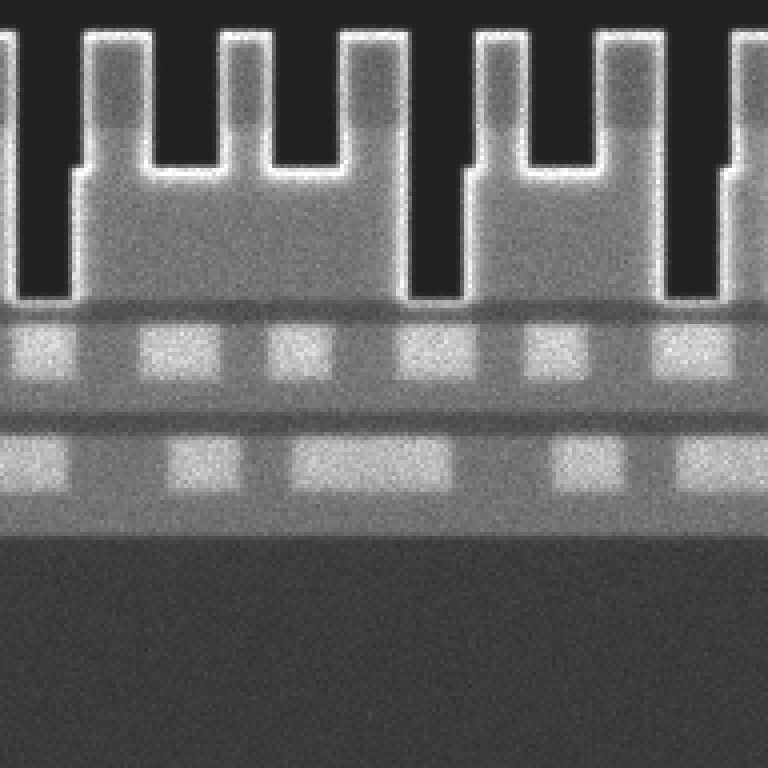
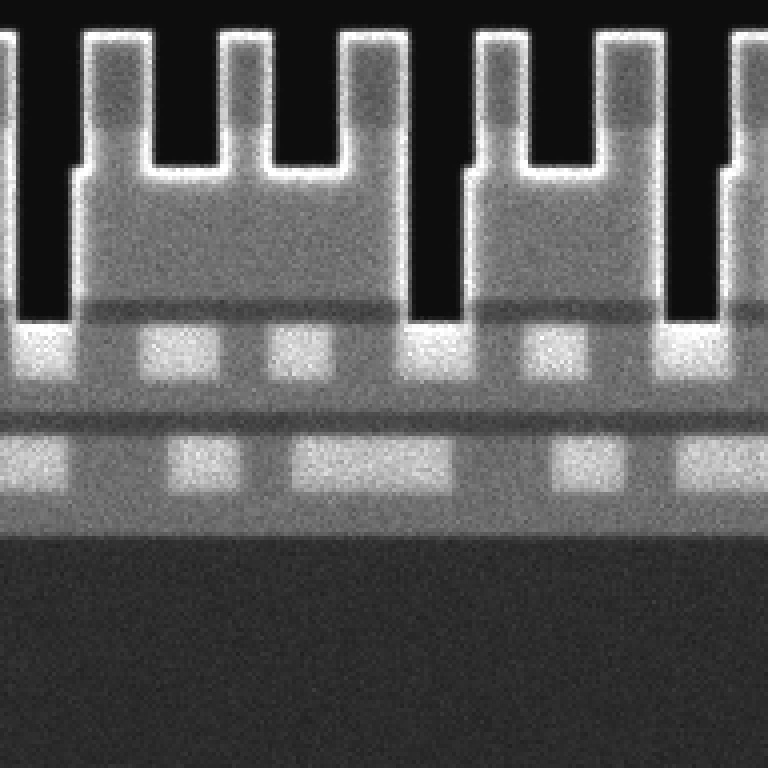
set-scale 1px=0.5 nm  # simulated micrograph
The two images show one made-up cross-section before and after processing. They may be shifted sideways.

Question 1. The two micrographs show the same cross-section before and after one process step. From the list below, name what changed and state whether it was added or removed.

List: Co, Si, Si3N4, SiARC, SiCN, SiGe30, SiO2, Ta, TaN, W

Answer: SiCN, removed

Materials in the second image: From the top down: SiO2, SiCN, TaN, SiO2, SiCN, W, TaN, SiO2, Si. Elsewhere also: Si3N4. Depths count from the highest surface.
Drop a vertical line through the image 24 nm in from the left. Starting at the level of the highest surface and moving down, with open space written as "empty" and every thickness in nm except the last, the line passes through empty 146, W 22, TaN 6, SiO2 16, SiCN 12, W 22, TaN 6, SiO2 22, Si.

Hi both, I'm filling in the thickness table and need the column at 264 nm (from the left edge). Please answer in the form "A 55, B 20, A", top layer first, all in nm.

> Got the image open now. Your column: empty 68, SiO2 66, SiCN 12, TaN 28, SiO2 16, SiCN 12, SiO2 50, Si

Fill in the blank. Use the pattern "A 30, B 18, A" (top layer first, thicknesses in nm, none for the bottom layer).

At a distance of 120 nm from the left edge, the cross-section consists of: Si3N4 48, SiO2 86, SiCN 12, SiO2 44, SiCN 12, SiO2 50, Si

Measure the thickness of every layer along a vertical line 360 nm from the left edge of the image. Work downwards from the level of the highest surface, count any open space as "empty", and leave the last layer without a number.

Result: empty 68, SiO2 66, SiCN 12, TaN 28, SiO2 16, SiCN 12, W 22, TaN 6, SiO2 22, Si